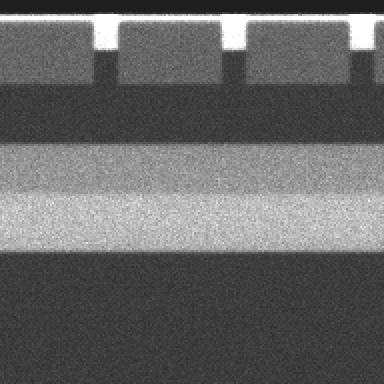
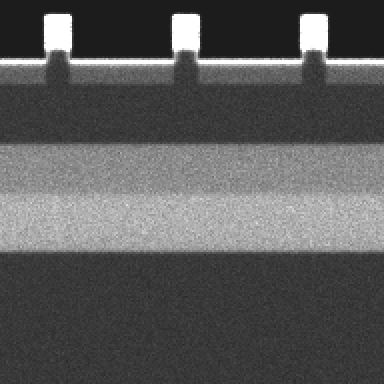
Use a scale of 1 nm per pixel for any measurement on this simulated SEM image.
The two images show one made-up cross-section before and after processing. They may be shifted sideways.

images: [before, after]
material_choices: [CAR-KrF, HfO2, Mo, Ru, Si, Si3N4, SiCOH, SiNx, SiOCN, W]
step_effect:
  removed: Si3N4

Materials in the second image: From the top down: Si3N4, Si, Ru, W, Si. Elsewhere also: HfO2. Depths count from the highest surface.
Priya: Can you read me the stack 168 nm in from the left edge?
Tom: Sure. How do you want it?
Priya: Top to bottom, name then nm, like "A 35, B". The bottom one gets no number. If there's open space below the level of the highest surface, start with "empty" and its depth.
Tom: empty 44, Si3N4 24, Si 60, Ru 50, W 58, Si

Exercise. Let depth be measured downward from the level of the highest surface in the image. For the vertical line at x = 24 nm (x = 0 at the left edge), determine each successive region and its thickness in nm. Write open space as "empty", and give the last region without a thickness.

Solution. empty 44, Si3N4 24, Si 60, Ru 50, W 58, Si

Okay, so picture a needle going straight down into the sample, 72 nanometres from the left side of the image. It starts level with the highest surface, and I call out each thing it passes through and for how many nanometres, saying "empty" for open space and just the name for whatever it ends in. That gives empty 44, Si3N4 24, Si 60, Ru 50, W 58, Si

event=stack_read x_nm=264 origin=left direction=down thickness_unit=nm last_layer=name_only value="empty 44, Si3N4 24, Si 60, Ru 50, W 58, Si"